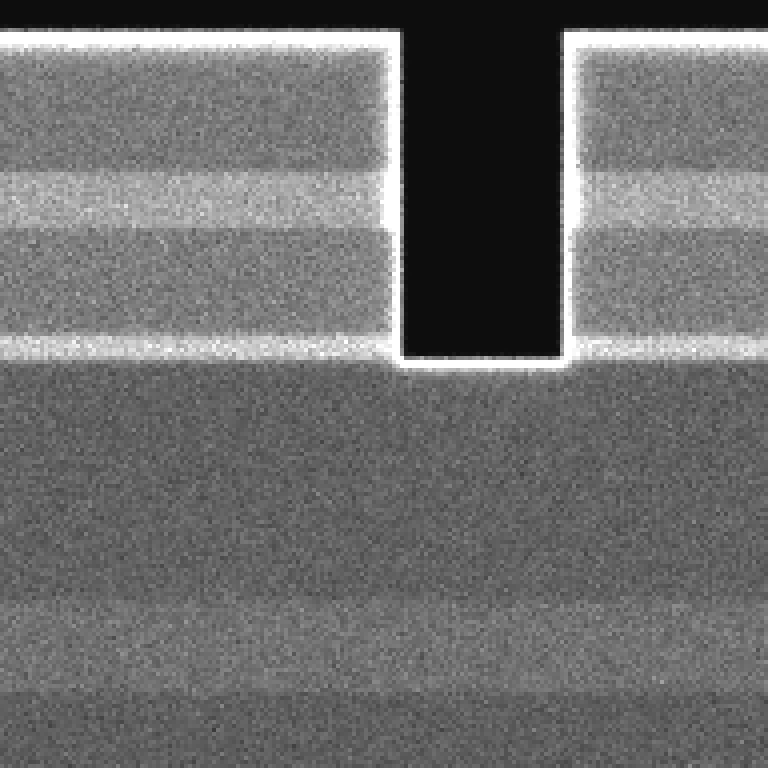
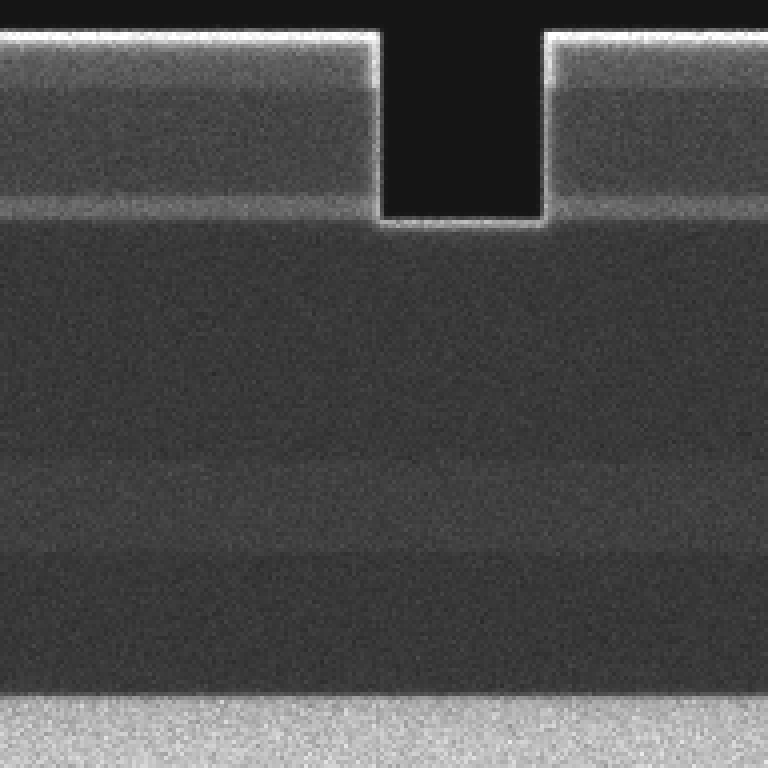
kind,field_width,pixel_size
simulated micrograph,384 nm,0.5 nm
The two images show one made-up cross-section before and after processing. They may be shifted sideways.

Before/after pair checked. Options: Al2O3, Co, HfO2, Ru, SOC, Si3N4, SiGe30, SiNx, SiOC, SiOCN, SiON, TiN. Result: removed SOC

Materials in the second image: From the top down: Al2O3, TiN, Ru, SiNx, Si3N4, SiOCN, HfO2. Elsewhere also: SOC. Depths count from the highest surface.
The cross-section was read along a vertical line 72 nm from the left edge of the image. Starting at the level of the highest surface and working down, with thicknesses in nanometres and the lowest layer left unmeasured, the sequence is Al2O3 28, TiN 54, Ru 12, SiNx 120, Si3N4 46, SiOCN 72, HfO2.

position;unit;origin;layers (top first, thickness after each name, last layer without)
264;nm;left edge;empty 94, SiNx 120, Si3N4 46, SiOCN 72, HfO2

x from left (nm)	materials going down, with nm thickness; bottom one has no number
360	Al2O3 28, TiN 54, Ru 12, SiNx 120, Si3N4 46, SiOCN 72, HfO2